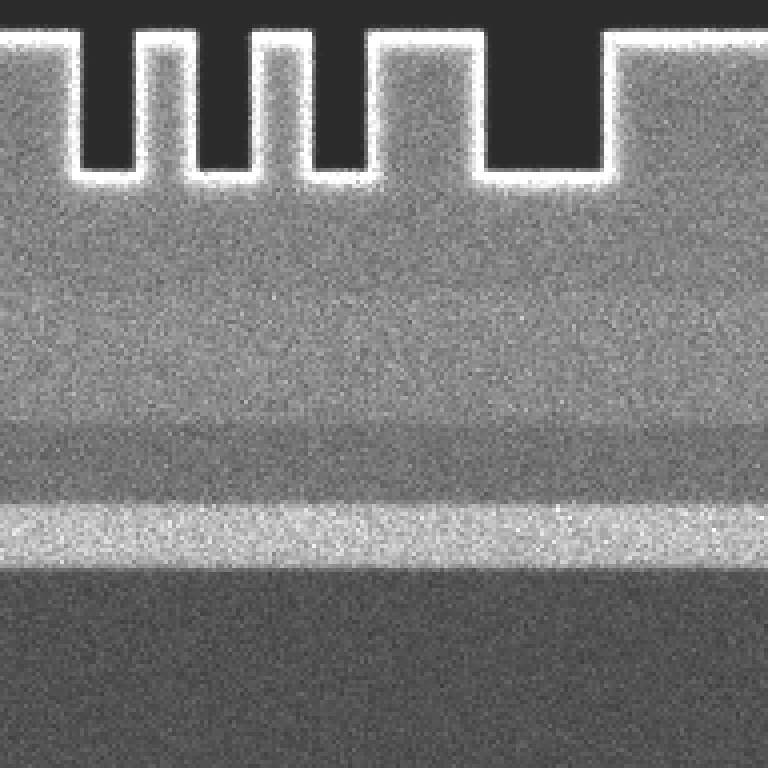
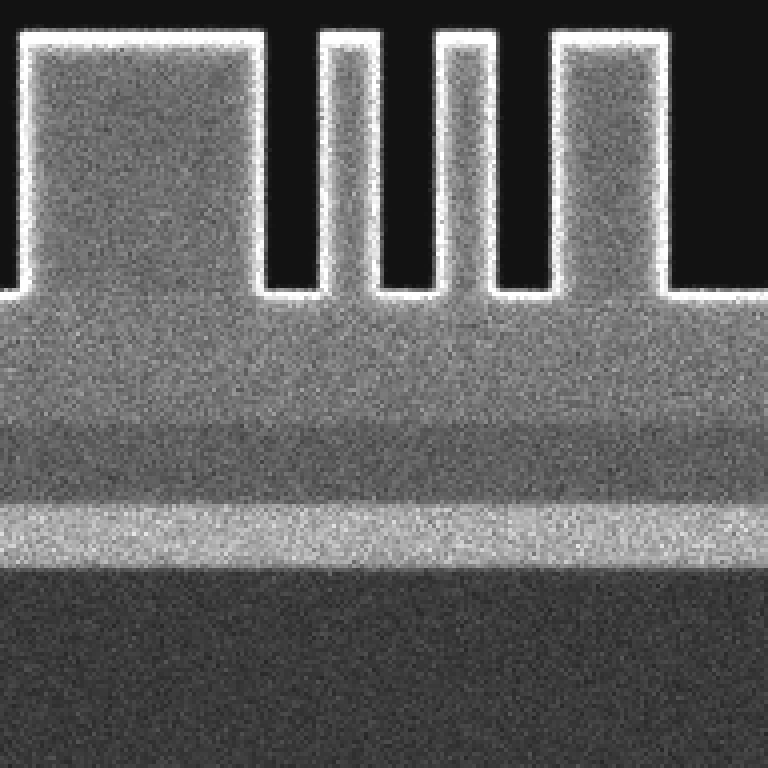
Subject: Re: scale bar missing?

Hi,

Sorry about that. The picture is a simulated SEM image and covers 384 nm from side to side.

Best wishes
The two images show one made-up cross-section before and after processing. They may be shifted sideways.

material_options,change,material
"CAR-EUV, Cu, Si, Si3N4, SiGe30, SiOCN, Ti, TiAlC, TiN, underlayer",removed,underlayer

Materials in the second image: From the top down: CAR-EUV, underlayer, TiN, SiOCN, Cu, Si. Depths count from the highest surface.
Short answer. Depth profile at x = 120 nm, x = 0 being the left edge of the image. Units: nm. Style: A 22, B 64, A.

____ CAR-EUV 70, underlayer 60, TiN 66, SiOCN 40, Cu 32, Si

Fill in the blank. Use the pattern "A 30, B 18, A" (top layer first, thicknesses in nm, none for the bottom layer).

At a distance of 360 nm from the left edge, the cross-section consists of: empty 130, TiN 66, SiOCN 40, Cu 32, Si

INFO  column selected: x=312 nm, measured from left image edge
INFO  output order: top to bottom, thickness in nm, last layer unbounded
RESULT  CAR-EUV 70, underlayer 60, TiN 66, SiOCN 40, Cu 32, Si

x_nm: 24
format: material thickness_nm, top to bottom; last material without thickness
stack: CAR-EUV 70, underlayer 60, TiN 66, SiOCN 40, Cu 32, Si